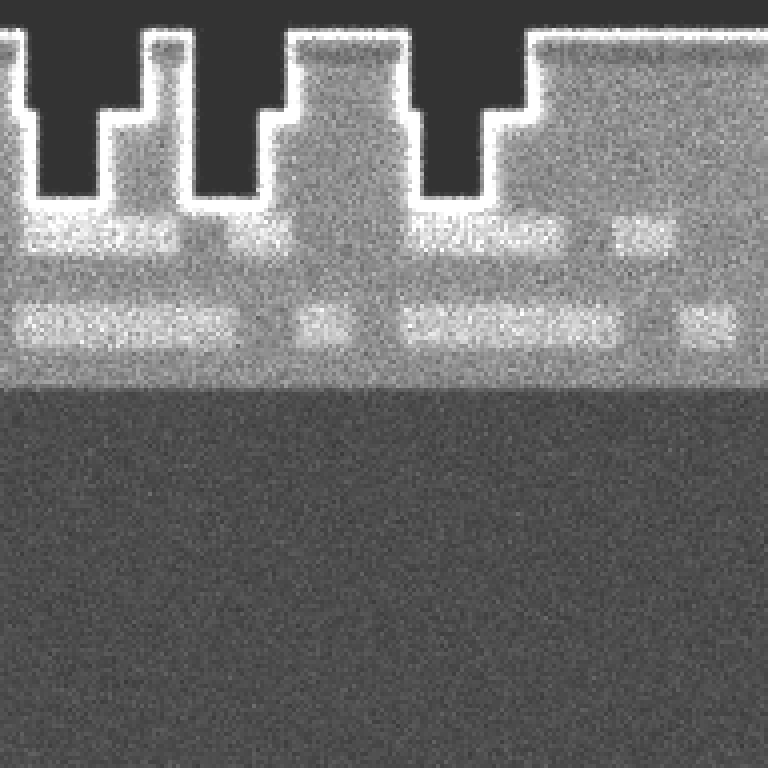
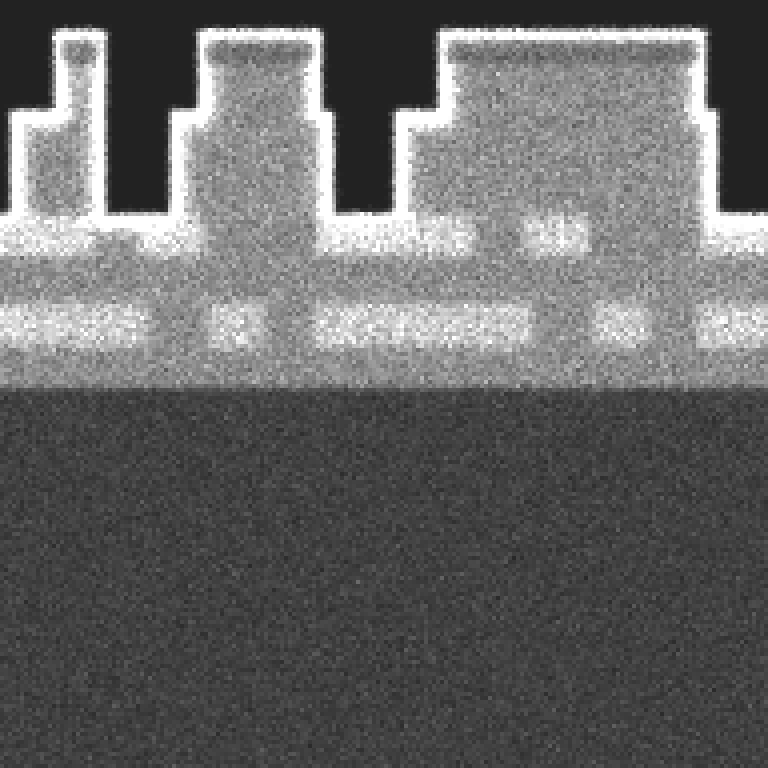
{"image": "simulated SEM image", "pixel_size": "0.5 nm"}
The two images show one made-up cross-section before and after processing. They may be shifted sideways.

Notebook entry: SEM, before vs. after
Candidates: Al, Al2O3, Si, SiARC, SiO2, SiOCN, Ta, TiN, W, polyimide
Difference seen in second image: Al2O3 removed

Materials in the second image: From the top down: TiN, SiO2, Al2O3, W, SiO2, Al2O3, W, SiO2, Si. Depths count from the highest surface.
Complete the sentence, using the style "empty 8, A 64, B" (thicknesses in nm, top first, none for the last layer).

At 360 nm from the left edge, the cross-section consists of empty 92, W 20, SiO2 16, Al2O3 8, W 22, SiO2 20, Si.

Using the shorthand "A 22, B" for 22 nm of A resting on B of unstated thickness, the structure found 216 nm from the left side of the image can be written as empty 40, SiO2 44, Al2O3 8, W 20, SiO2 16, Al2O3 8, W 22, SiO2 20, Si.